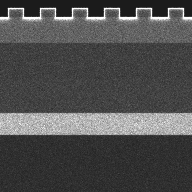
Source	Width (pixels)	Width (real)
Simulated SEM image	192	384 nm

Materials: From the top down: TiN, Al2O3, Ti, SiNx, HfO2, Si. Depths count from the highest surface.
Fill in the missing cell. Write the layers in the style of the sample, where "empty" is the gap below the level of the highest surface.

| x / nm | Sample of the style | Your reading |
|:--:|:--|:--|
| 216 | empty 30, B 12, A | TiN 18, Al2O3 52, Ti 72, SiNx 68, HfO2 44, Si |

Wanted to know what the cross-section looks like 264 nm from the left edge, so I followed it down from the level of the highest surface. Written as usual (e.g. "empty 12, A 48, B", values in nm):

empty 18, Al2O3 52, Ti 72, SiNx 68, HfO2 44, Si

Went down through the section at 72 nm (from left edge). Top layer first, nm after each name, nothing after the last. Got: empty 18, Al2O3 52, Ti 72, SiNx 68, HfO2 44, Si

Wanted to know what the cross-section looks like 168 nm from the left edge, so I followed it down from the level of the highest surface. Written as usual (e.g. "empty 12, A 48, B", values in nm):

TiN 18, Al2O3 52, Ti 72, SiNx 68, HfO2 44, Si